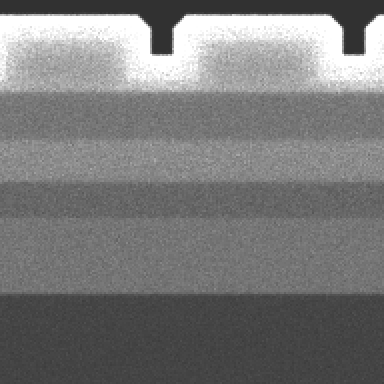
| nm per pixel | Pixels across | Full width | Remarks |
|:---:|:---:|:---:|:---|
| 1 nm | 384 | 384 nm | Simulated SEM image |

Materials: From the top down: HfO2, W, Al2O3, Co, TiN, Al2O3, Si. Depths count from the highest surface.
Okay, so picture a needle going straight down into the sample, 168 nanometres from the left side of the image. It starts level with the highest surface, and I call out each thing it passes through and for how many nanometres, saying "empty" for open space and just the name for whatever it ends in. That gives empty 40, HfO2 24, W 12, Al2O3 48, Co 42, TiN 36, Al2O3 76, Si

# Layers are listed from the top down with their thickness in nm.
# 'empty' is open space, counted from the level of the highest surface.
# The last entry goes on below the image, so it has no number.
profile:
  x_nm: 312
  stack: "HfO2 24, W 52, Al2O3 48, Co 42, TiN 36, Al2O3 76, Si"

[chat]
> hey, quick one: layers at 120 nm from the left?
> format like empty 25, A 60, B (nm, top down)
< HfO2 24, W 52, Al2O3 48, Co 42, TiN 36, Al2O3 76, Si